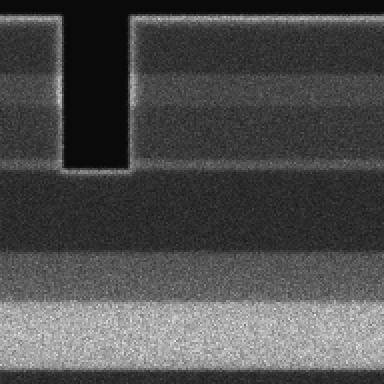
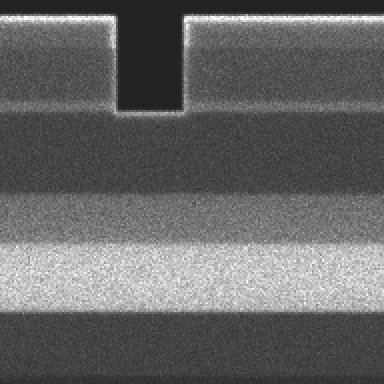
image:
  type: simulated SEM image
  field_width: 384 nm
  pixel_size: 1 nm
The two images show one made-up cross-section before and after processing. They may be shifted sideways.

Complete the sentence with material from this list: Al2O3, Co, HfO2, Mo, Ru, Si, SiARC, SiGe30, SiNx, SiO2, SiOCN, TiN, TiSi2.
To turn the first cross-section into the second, SiARC must be removed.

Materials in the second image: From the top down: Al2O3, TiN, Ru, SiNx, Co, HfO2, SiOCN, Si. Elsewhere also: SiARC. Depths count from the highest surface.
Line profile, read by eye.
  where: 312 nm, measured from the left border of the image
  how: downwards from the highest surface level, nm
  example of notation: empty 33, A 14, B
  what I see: Al2O3 32, TiN 54, Ru 10, SiNx 82, Co 50, HfO2 68, SiOCN 64, Si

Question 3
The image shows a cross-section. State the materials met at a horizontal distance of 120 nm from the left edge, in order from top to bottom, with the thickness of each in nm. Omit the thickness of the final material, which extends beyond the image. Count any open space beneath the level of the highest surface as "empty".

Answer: empty 96, SiNx 82, Co 50, HfO2 68, SiOCN 64, Si